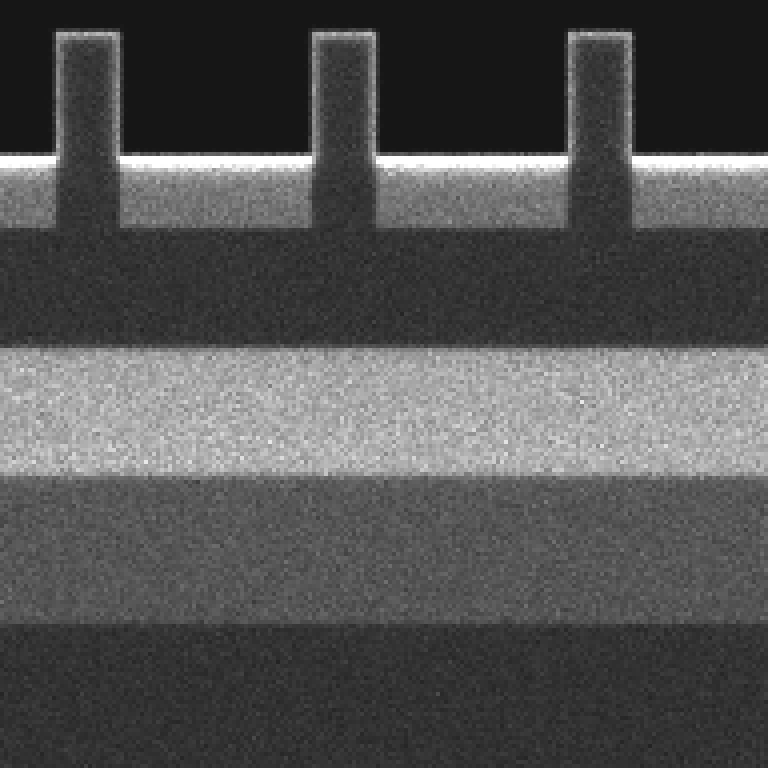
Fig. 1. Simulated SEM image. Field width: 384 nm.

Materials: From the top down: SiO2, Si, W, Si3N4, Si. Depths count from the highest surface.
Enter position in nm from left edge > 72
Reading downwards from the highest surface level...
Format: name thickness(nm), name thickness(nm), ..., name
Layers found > empty 62, SiO2 36, Si 60, W 64, Si3N4 74, Si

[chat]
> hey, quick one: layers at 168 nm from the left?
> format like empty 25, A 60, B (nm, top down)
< Si 158, W 64, Si3N4 74, Si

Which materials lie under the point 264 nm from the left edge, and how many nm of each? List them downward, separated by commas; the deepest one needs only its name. empty 62, SiO2 36, Si 60, W 64, Si3N4 74, Si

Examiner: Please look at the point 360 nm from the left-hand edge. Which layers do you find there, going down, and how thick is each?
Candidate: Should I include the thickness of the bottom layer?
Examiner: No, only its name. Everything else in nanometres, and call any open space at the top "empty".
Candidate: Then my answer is empty 62, SiO2 36, Si 60, W 64, Si3N4 74, Si